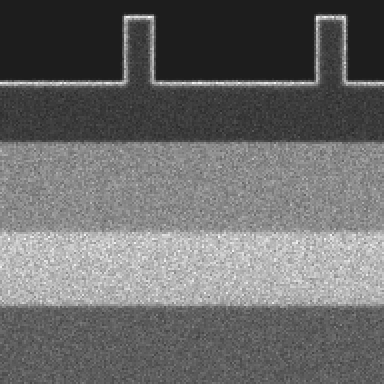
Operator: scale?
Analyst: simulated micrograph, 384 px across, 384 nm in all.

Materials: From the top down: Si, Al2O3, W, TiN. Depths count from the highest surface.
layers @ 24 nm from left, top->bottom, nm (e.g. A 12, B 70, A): empty 66, Si 60, Al2O3 90, W 74, TiN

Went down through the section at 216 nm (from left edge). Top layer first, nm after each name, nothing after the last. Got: empty 66, Si 60, Al2O3 90, W 74, TiN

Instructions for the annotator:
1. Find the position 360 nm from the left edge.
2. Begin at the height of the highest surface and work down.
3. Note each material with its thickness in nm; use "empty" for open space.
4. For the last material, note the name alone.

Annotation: empty 66, Si 60, Al2O3 90, W 74, TiN